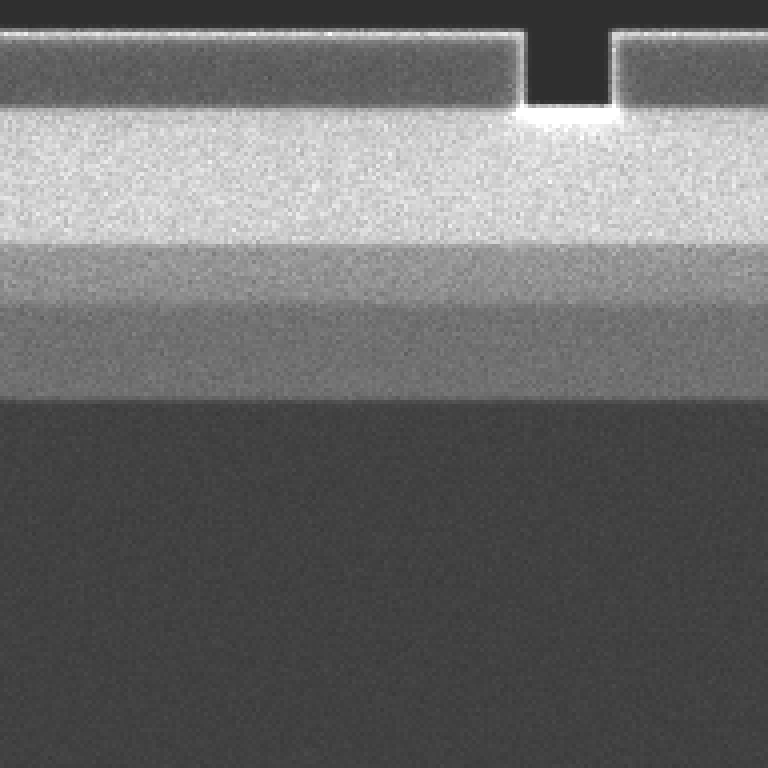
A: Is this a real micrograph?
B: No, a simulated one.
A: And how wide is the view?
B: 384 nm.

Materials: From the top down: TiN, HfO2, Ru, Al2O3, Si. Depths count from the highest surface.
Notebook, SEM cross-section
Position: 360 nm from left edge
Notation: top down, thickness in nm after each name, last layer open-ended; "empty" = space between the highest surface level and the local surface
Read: TiN 38, HfO2 68, Ru 30, Al2O3 48, Si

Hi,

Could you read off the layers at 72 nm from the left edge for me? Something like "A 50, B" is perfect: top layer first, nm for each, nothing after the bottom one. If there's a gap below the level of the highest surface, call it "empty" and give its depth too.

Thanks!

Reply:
TiN 38, HfO2 68, Ru 30, Al2O3 48, Si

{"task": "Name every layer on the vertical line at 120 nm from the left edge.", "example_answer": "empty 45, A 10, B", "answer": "TiN 38, HfO2 68, Ru 30, Al2O3 48, Si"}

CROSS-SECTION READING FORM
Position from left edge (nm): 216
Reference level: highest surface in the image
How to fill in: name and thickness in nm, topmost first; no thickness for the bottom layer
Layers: TiN 38, HfO2 68, Ru 30, Al2O3 48, Si